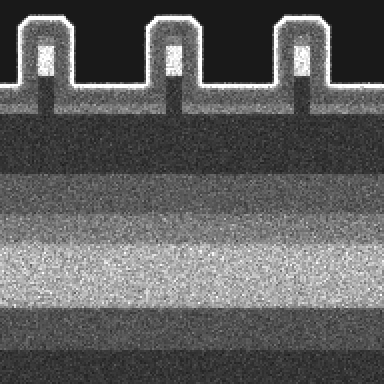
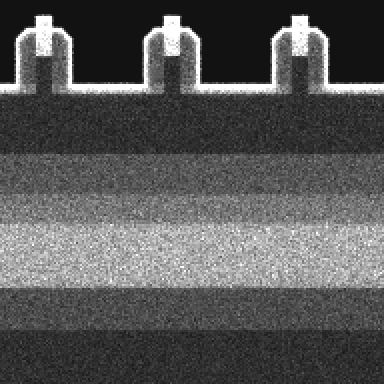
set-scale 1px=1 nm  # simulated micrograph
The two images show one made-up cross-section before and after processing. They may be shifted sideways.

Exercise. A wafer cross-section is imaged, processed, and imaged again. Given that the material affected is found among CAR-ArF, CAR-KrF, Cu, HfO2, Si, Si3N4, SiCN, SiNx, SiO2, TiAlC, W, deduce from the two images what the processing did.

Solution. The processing removed Si3N4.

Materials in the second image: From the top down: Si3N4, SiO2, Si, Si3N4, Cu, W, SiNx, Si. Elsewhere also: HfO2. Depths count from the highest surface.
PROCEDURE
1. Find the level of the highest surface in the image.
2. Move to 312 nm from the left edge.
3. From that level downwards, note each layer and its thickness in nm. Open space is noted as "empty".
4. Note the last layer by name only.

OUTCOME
empty 12, Si3N4 56, SiO2 10, Si 60, Si3N4 40, Cu 30, W 64, SiNx 42, Si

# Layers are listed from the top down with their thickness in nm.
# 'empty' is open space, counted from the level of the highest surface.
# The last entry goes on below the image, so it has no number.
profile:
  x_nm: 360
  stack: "empty 68, SiO2 10, Si 60, Si3N4 40, Cu 30, W 64, SiNx 42, Si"